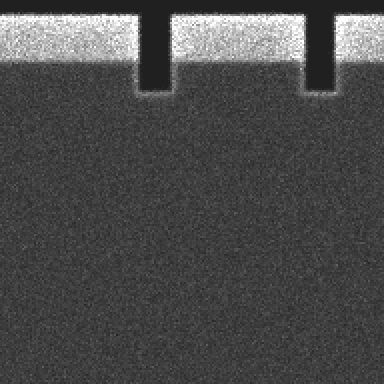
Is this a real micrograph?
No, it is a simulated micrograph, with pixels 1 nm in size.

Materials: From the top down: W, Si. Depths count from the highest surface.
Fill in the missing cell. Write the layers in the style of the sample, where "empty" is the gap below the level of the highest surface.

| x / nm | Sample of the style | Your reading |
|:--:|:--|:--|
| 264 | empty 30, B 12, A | W 46, Si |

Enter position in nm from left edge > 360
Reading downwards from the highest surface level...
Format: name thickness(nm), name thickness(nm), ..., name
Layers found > W 46, Si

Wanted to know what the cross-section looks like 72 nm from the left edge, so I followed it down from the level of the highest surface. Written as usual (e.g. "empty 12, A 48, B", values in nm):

W 46, Si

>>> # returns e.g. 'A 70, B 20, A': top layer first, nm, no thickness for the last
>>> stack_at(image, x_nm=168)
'empty 76, Si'